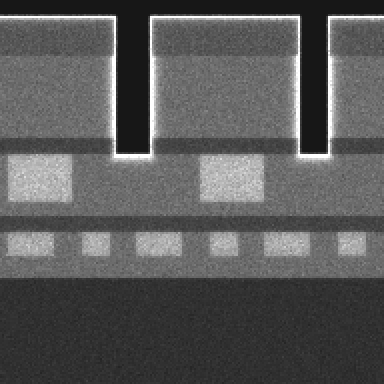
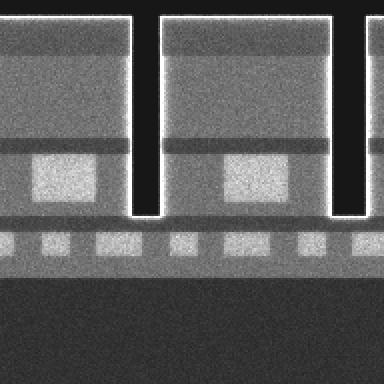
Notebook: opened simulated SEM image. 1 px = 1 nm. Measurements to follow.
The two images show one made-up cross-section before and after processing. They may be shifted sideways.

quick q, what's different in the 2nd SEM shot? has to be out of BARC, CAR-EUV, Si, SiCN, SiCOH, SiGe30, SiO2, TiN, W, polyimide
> SiO2 removed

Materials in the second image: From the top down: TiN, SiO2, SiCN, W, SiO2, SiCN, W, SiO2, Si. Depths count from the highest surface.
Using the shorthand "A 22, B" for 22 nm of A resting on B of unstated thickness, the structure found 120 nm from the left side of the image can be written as TiN 40, SiO2 82, SiCN 16, SiO2 62, SiCN 16, W 24, SiO2 22, Si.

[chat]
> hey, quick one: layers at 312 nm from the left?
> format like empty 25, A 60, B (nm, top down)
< TiN 40, SiO2 82, SiCN 16, SiO2 62, SiCN 16, W 24, SiO2 22, Si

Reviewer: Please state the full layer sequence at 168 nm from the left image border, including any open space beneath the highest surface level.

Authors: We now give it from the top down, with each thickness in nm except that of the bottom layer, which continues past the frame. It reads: TiN 40, SiO2 82, SiCN 16, SiO2 62, SiCN 16, SiO2 46, Si